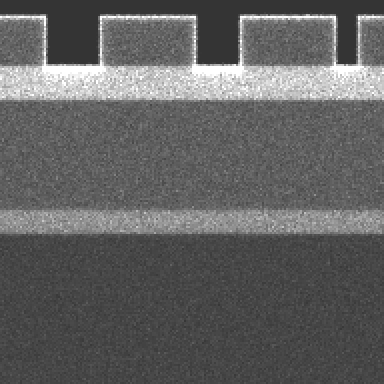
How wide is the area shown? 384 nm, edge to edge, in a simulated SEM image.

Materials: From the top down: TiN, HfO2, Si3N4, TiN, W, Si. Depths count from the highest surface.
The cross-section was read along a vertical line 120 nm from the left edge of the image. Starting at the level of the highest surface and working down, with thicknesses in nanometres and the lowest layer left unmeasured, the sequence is TiN 50, HfO2 34, Si3N4 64, TiN 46, W 24, Si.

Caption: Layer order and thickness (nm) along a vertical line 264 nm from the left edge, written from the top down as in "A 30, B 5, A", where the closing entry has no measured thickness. TiN 50, HfO2 34, Si3N4 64, TiN 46, W 24, Si